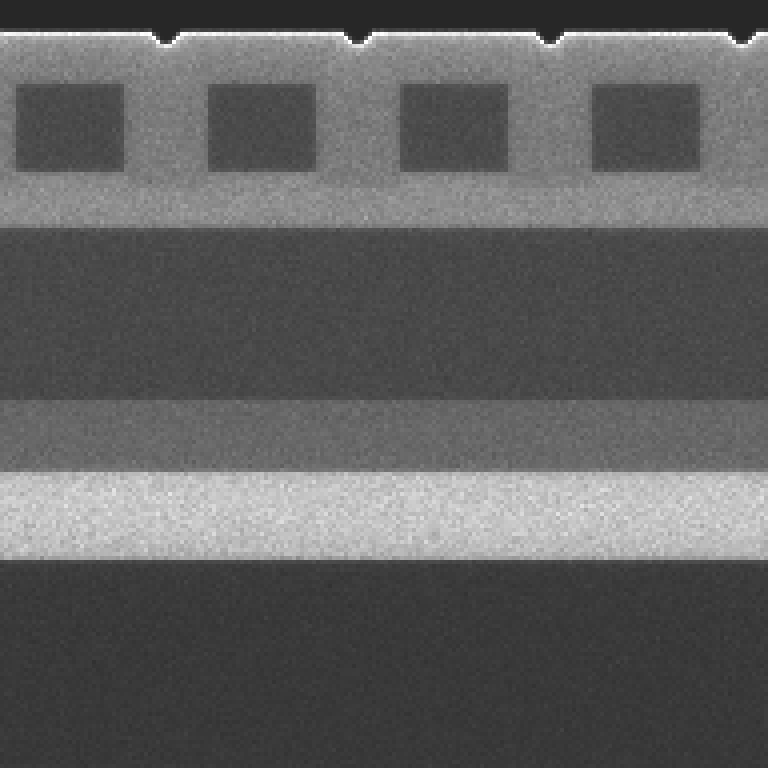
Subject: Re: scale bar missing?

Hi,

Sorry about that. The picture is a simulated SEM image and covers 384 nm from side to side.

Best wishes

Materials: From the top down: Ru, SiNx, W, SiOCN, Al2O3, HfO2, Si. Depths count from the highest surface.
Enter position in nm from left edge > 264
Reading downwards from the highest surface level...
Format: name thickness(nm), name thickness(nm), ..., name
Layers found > Ru 78, W 20, SiOCN 86, Al2O3 36, HfO2 44, Si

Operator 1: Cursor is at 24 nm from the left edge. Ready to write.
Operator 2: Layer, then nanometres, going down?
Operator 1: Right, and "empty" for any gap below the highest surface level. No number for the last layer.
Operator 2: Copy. Ru 26, SiNx 44, W 28, SiOCN 86, Al2O3 36, HfO2 44, Si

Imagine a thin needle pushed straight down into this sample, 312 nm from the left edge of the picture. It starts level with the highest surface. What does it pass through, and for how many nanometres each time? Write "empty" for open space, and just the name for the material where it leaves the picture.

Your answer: Ru 26, SiNx 44, W 28, SiOCN 86, Al2O3 36, HfO2 44, Si